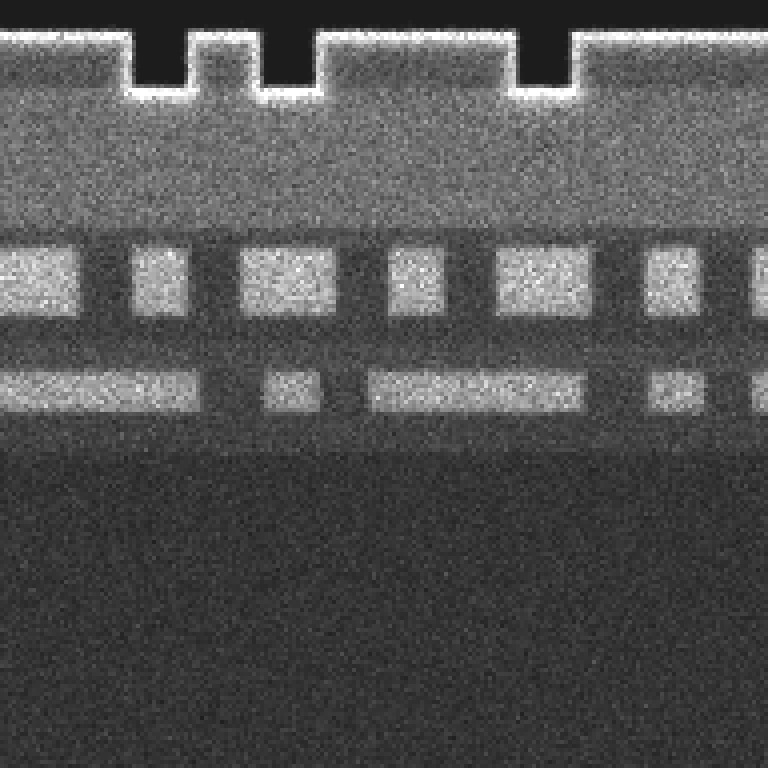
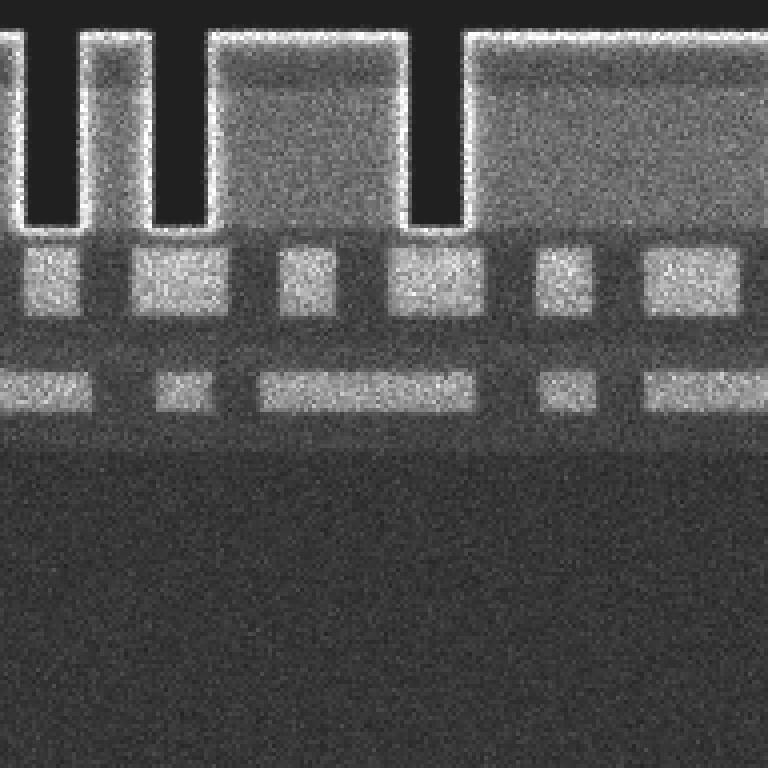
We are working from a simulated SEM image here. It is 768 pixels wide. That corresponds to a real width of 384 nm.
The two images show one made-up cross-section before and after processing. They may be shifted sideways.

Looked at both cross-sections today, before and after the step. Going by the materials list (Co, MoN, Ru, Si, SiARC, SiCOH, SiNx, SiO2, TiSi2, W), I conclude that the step removed SiO2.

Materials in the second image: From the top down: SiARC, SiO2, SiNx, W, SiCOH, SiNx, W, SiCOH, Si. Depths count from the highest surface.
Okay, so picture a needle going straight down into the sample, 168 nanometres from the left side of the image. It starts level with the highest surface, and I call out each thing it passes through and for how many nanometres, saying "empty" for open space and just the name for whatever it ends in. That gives SiARC 28, SiO2 70, SiNx 10, SiCOH 48, SiNx 14, W 20, SiCOH 20, Si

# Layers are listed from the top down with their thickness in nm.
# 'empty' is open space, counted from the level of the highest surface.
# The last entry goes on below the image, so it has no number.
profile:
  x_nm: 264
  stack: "SiARC 28, SiO2 70, SiNx 10, SiCOH 48, SiNx 14, SiCOH 40, Si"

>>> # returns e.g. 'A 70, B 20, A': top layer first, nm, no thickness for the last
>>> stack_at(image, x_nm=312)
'SiARC 28, SiO2 70, SiNx 10, SiCOH 48, SiNx 14, SiCOH 40, Si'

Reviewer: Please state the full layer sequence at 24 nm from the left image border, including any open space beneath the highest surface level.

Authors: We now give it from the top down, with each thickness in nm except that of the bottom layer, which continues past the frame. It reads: empty 98, SiNx 10, W 34, SiCOH 14, SiNx 14, W 20, SiCOH 20, Si